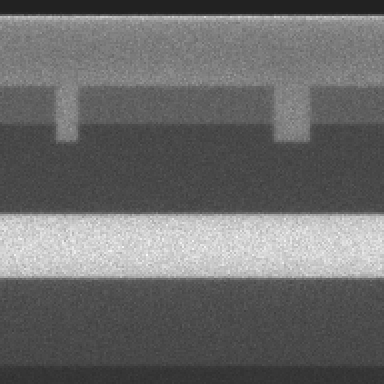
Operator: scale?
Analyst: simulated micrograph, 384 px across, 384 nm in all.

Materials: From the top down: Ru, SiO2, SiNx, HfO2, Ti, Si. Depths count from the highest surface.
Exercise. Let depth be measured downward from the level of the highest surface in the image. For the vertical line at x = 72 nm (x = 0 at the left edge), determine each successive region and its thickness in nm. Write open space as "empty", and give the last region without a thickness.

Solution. Ru 126, SiNx 72, HfO2 64, Ti 88, Si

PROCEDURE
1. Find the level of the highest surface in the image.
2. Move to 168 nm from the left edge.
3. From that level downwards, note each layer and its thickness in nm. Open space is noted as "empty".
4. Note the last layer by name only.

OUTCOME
Ru 70, SiO2 38, SiNx 90, HfO2 64, Ti 88, Si